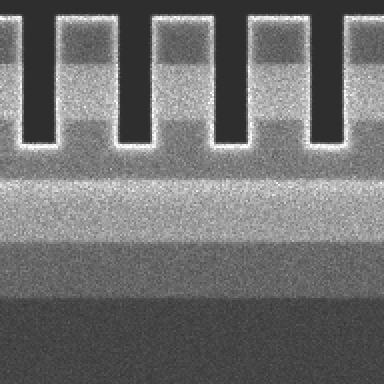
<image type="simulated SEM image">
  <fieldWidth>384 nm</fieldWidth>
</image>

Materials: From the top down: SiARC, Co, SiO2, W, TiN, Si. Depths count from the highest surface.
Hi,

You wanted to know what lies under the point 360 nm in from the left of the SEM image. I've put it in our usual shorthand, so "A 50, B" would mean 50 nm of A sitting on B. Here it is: SiARC 48, Co 56, SiO2 60, W 62, TiN 56, Si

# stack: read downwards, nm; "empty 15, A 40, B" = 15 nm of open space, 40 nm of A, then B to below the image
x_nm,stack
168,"SiARC 48, Co 56, SiO2 60, W 62, TiN 56, Si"